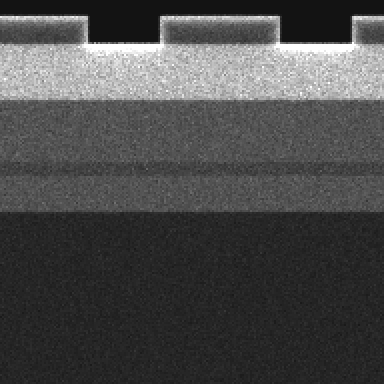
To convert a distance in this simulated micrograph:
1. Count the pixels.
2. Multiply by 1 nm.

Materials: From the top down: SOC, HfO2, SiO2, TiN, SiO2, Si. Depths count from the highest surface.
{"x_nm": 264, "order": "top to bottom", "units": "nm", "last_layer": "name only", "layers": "SOC 28, HfO2 56, SiO2 62, TiN 14, SiO2 36, Si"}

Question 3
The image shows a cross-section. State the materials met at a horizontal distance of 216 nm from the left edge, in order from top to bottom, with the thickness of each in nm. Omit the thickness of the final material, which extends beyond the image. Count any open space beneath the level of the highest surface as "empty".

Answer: SOC 28, HfO2 56, SiO2 62, TiN 14, SiO2 36, Si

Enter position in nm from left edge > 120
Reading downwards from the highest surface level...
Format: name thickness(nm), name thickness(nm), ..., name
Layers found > empty 28, HfO2 56, SiO2 62, TiN 14, SiO2 36, Si